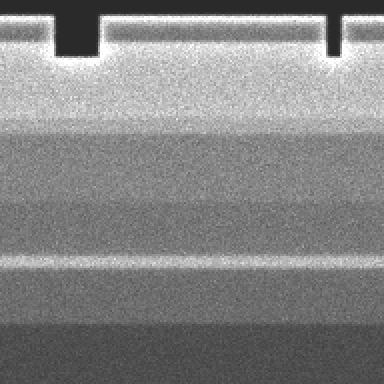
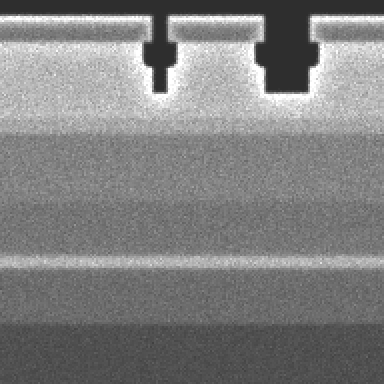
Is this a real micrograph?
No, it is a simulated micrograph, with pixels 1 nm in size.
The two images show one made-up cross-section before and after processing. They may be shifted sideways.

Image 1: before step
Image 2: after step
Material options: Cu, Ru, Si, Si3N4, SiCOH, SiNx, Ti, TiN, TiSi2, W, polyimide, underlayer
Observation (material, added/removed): W, removed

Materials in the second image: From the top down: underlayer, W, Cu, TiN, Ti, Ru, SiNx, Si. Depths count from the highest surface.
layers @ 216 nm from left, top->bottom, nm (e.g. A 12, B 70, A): underlayer 26, W 76, Cu 16, TiN 68, Ti 54, Ru 12, SiNx 56, Si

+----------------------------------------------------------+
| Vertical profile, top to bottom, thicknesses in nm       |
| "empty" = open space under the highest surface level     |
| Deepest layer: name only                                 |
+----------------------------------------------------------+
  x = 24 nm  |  underlayer 26, W 76, Cu 16, TiN 68, Ti 54, Ru 12, SiNx 56, Si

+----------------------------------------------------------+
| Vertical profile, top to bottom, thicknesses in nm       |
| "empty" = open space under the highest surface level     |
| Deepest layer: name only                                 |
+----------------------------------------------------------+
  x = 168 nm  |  underlayer 26, empty 26, W 50, Cu 16, TiN 68, Ti 54, Ru 12, SiNx 56, Si